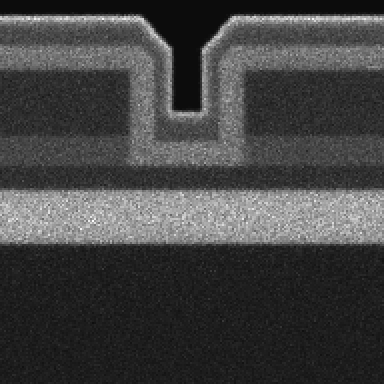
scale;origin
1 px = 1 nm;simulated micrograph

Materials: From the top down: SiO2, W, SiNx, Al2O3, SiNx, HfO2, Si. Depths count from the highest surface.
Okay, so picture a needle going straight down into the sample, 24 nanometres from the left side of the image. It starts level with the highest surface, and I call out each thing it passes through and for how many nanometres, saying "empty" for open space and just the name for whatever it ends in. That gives SiO2 30, W 24, SiNx 66, Al2O3 30, SiNx 24, HfO2 54, Si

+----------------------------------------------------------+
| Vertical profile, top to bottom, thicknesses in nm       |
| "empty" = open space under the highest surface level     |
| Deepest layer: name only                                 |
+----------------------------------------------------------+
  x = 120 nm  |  SiO2 30, W 24, SiNx 66, Al2O3 30, SiNx 24, HfO2 54, Si